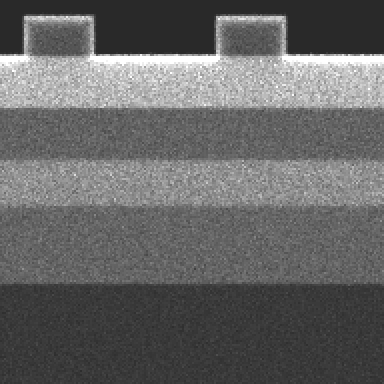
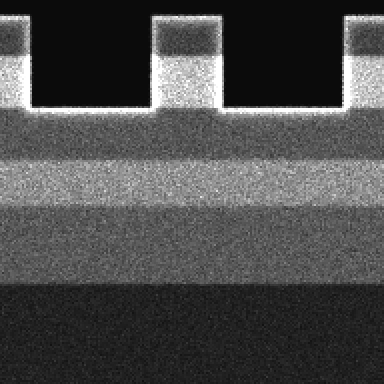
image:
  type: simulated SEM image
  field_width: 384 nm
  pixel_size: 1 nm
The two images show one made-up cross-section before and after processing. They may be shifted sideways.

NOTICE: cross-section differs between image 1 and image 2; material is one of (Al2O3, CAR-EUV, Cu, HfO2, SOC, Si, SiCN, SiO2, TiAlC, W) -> removed: HfO2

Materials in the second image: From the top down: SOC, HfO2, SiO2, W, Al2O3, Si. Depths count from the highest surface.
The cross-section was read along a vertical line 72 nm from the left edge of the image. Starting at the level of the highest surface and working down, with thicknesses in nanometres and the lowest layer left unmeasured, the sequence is empty 92, SiO2 52, W 46, Al2O3 78, Si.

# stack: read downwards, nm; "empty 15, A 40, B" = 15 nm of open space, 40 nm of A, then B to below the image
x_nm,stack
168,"SOC 40, HfO2 52, SiO2 52, W 46, Al2O3 78, Si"